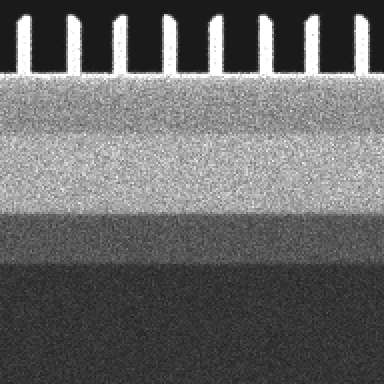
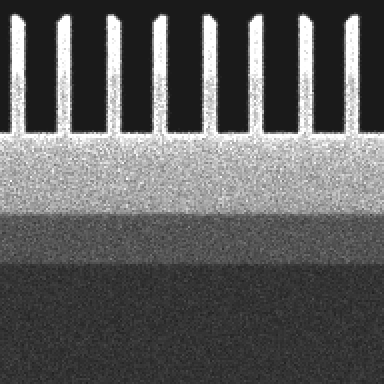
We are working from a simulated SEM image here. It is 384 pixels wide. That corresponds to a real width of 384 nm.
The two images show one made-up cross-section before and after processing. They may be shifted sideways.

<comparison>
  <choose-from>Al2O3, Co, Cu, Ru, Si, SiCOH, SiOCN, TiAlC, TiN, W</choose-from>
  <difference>Ru removed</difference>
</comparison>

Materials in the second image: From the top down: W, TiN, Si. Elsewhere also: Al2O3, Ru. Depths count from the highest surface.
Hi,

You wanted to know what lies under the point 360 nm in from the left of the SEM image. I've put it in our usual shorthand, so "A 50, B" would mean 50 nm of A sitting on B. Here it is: empty 118, W 80, TiN 50, Si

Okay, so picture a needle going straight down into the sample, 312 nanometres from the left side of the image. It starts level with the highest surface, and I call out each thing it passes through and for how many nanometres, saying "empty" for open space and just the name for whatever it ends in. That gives empty 118, W 80, TiN 50, Si